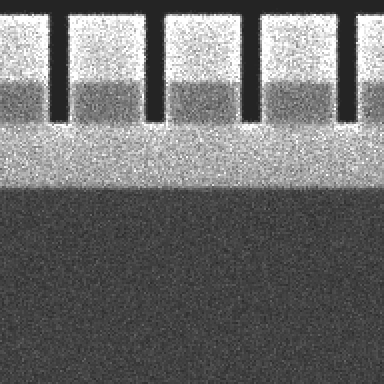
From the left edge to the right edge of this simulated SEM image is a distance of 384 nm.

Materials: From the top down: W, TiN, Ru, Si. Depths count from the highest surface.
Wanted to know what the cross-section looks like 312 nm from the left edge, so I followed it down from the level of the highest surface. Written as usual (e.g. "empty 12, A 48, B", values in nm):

W 66, TiN 42, Ru 64, Si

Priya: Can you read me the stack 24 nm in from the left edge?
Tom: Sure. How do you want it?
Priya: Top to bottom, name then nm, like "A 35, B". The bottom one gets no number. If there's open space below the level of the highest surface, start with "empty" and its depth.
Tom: W 66, TiN 42, Ru 64, Si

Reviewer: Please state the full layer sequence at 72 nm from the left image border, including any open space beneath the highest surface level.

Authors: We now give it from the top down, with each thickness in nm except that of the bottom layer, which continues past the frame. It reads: W 66, TiN 42, Ru 64, Si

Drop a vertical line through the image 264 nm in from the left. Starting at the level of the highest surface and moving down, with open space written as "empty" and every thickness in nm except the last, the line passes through W 66, TiN 42, Ru 64, Si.